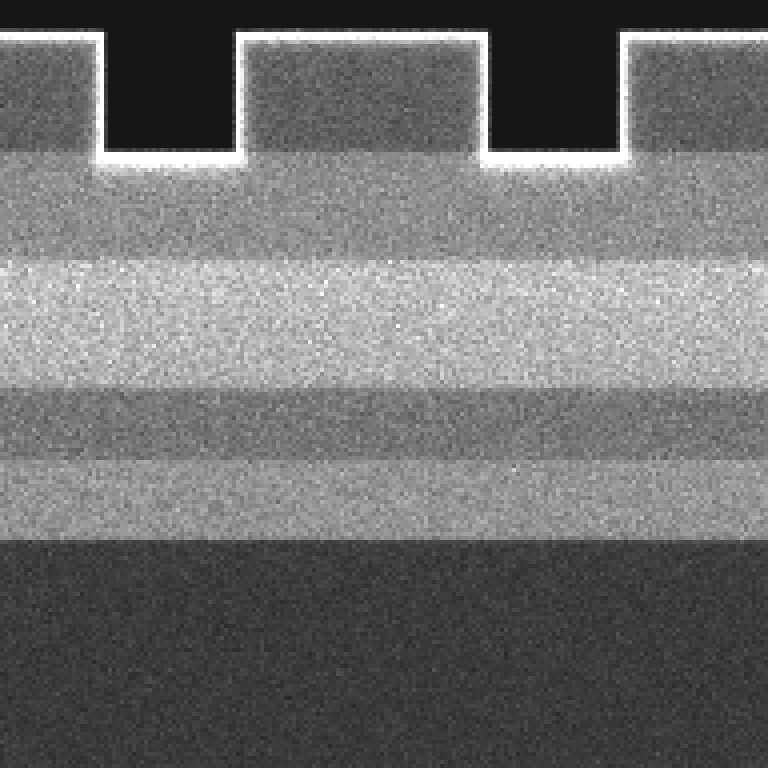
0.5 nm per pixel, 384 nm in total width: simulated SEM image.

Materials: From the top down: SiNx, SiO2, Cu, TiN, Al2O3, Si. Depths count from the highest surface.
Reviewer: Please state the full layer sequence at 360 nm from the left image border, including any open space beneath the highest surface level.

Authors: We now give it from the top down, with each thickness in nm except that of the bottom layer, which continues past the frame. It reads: SiNx 60, SiO2 54, Cu 64, TiN 36, Al2O3 40, Si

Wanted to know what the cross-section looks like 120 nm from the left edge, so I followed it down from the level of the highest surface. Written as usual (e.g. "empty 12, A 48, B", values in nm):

SiNx 60, SiO2 54, Cu 64, TiN 36, Al2O3 40, Si